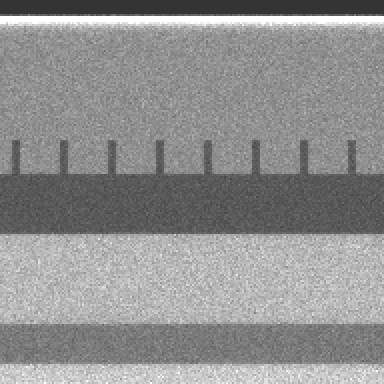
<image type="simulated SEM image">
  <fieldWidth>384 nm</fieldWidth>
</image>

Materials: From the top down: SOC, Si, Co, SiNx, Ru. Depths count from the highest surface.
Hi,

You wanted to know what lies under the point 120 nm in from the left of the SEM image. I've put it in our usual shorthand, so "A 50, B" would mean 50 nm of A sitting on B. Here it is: SOC 158, Si 60, Co 90, SiNx 40, Ru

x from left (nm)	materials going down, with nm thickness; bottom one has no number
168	SOC 158, Si 60, Co 90, SiNx 40, Ru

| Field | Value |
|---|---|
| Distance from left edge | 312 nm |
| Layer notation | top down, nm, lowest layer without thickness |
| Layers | SOC 158, Si 60, Co 90, SiNx 40, Ru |